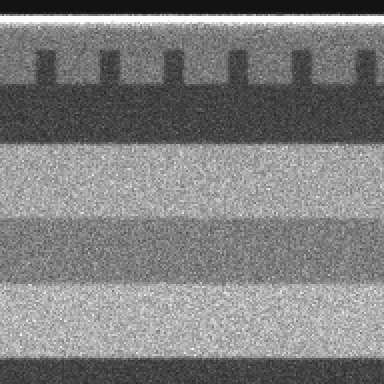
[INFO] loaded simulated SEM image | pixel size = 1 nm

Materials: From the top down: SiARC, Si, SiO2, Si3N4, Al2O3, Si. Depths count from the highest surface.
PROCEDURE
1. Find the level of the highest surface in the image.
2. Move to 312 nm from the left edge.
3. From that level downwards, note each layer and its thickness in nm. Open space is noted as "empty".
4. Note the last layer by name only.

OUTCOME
SiARC 68, Si 60, SiO2 74, Si3N4 66, Al2O3 74, Si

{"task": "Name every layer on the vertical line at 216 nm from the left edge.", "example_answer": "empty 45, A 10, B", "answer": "SiARC 68, Si 60, SiO2 74, Si3N4 66, Al2O3 74, Si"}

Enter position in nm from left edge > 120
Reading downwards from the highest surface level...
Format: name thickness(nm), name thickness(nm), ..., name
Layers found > SiARC 68, Si 60, SiO2 74, Si3N4 66, Al2O3 74, Si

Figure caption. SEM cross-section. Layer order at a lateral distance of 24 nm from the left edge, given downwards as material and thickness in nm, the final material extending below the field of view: SiARC 68, Si 60, SiO2 74, Si3N4 66, Al2O3 74, Si